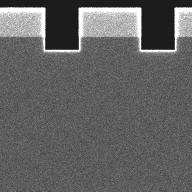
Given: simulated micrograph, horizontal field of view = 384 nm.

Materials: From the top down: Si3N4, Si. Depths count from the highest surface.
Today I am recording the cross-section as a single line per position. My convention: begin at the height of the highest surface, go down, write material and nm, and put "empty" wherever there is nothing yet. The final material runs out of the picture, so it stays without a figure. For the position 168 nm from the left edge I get Si3N4 58, Si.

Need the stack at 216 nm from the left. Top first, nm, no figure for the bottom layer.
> Si3N4 58, Si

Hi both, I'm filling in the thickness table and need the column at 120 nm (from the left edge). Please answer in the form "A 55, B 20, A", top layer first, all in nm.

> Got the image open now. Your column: empty 84, Si